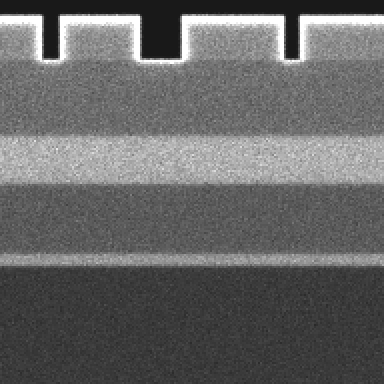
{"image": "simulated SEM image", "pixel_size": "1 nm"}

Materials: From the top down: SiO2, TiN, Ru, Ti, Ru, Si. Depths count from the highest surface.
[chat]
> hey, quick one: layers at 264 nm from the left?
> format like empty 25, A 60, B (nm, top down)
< SiO2 44, TiN 76, Ru 48, Ti 70, Ru 12, Si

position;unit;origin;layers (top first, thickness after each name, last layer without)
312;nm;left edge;SiO2 44, TiN 76, Ru 48, Ti 70, Ru 12, Si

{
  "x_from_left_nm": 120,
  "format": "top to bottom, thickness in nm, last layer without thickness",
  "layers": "SiO2 44, TiN 76, Ru 48, Ti 70, Ru 12, Si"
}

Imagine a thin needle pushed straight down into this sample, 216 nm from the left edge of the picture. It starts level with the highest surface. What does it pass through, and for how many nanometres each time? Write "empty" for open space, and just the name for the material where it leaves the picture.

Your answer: SiO2 44, TiN 76, Ru 48, Ti 70, Ru 12, Si